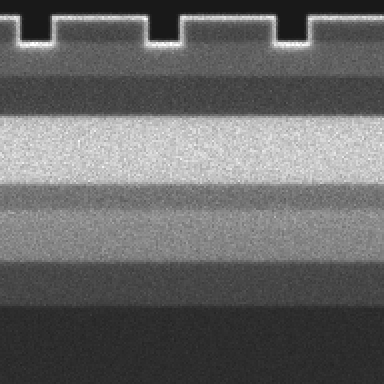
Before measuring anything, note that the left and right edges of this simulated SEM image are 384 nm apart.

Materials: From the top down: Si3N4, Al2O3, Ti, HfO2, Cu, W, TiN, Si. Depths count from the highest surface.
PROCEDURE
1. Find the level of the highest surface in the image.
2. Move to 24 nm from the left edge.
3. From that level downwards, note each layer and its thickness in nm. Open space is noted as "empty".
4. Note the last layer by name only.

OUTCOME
empty 26, Al2O3 34, Ti 40, HfO2 68, Cu 26, W 52, TiN 44, Si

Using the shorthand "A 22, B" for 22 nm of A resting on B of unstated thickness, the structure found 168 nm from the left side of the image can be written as empty 26, Al2O3 34, Ti 40, HfO2 68, Cu 26, W 52, TiN 44, Si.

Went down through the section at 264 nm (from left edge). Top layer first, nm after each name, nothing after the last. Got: Si3N4 26, Al2O3 34, Ti 40, HfO2 68, Cu 26, W 52, TiN 44, Si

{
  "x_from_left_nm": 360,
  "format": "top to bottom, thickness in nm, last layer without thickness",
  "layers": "Si3N4 26, Al2O3 34, Ti 40, HfO2 68, Cu 26, W 52, TiN 44, Si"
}